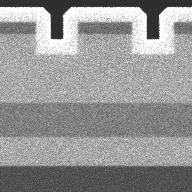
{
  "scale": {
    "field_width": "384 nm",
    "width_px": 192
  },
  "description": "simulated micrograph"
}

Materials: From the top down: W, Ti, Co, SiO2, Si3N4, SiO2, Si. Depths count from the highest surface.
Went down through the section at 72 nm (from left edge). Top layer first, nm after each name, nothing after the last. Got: W 92, Co 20, SiO2 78, Si3N4 68, SiO2 58, Si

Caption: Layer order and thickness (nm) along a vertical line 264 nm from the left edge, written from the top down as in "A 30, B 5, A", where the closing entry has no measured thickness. W 92, Co 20, SiO2 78, Si3N4 68, SiO2 58, Si